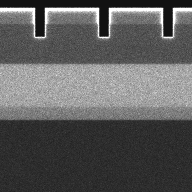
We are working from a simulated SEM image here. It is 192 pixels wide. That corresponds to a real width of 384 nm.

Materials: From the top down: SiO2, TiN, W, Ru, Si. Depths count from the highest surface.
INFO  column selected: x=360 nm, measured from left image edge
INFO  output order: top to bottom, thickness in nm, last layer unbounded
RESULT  SiO2 32, TiN 80, W 86, Ru 26, Si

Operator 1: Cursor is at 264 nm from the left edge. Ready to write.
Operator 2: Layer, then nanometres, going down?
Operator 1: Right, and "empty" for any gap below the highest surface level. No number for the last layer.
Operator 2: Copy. SiO2 32, TiN 80, W 86, Ru 26, Si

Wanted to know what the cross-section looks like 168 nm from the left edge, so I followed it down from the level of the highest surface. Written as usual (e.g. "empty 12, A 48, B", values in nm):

SiO2 32, TiN 80, W 86, Ru 26, Si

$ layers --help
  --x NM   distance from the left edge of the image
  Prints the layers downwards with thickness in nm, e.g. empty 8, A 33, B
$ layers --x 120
SiO2 32, TiN 80, W 86, Ru 26, Si